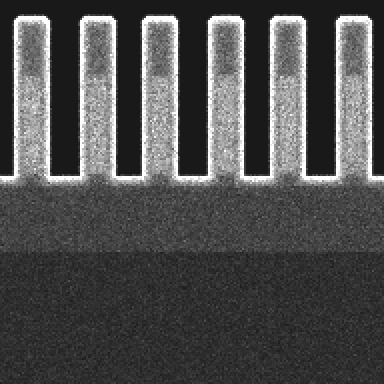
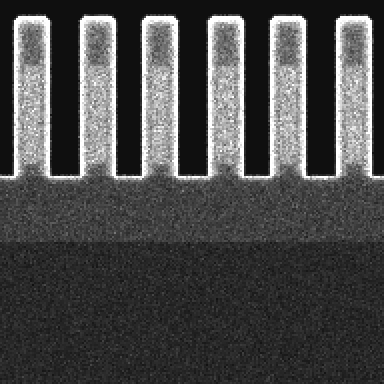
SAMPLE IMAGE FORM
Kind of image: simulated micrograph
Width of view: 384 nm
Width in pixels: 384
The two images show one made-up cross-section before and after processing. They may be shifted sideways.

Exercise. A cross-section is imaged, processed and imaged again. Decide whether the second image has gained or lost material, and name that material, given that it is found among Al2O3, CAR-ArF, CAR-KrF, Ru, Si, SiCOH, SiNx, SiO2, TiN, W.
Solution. removed: Al2O3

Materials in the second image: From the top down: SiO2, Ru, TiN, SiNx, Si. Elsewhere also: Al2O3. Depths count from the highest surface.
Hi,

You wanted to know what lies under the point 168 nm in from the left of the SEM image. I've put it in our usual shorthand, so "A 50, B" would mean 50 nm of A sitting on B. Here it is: Al2O3 160, SiNx 66, Si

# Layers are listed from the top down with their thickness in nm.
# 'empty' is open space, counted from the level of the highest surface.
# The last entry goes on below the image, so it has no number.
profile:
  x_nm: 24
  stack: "SiO2 50, Ru 98, TiN 12, SiNx 66, Si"